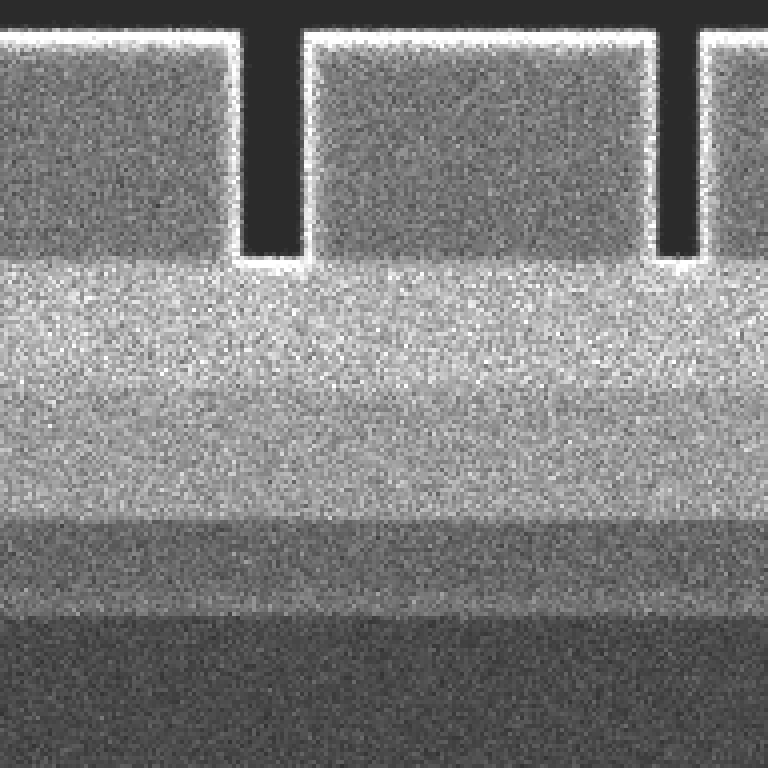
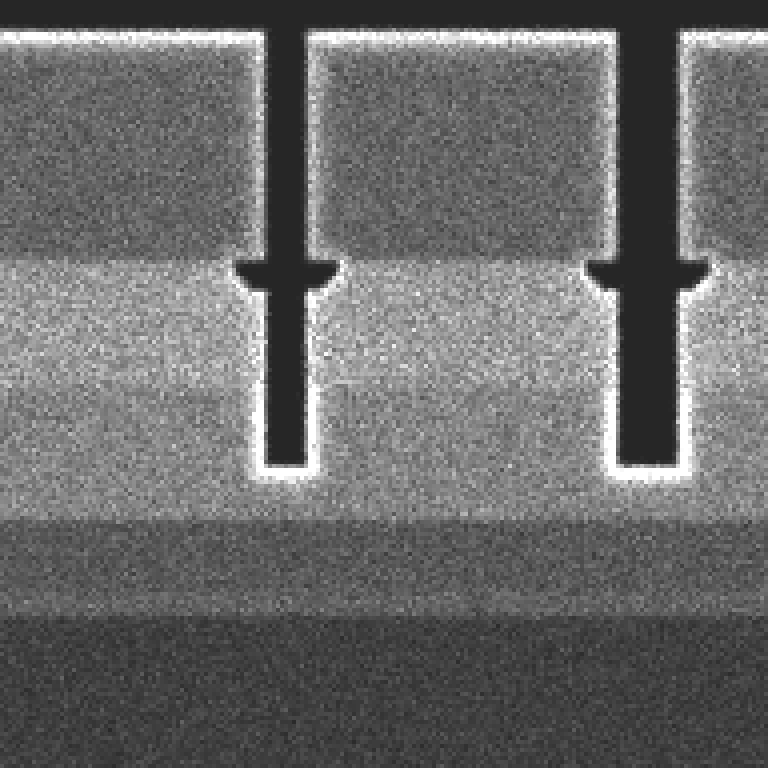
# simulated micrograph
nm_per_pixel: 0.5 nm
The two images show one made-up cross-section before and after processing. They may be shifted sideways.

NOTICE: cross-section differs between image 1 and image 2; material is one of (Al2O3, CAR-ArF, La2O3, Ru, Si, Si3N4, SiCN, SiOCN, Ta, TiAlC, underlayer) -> removed: Al2O3 and Ru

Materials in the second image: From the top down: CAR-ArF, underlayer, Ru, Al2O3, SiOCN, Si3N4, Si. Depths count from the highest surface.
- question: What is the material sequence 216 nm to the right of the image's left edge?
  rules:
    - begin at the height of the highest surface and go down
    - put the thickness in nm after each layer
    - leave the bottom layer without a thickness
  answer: CAR-ArF 72, underlayer 42, Ru 64, Al2O3 66, SiOCN 36, Si3N4 12, Si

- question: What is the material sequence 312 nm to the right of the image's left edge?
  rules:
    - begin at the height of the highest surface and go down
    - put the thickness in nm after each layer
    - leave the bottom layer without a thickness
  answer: empty 218, Al2O3 26, SiOCN 36, Si3N4 12, Si